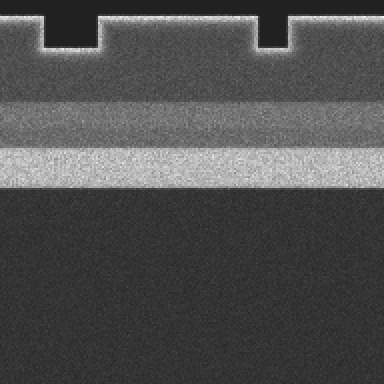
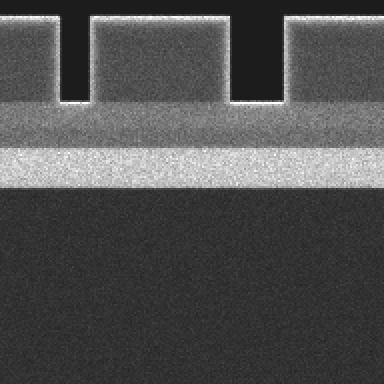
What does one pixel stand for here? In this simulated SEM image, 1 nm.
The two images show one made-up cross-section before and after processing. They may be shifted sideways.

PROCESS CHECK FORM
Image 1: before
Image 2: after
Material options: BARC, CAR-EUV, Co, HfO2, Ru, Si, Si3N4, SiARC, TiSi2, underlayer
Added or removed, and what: removed, underlayer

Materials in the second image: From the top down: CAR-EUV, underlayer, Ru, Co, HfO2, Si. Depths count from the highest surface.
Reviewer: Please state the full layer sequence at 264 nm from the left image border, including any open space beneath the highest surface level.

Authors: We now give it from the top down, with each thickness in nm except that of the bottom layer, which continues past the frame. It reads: empty 86, Ru 26, Co 20, HfO2 40, Si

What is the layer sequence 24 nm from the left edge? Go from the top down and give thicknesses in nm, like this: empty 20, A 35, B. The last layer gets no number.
CAR-EUV 32, underlayer 54, Ru 26, Co 20, HfO2 40, Si